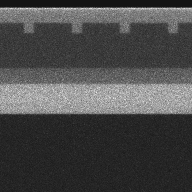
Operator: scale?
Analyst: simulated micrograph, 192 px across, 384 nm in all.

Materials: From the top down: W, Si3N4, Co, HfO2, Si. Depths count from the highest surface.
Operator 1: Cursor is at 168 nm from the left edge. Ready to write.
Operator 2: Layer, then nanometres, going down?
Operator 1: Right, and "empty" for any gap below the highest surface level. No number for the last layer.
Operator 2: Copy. W 30, Si3N4 90, Co 32, HfO2 60, Si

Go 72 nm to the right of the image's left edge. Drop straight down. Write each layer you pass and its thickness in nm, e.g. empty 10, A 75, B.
W 30, Si3N4 90, Co 32, HfO2 60, Si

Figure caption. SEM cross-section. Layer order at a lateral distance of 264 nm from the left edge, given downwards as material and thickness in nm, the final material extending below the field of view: W 30, Si3N4 90, Co 32, HfO2 60, Si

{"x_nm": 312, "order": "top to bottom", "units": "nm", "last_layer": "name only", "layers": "W 30, Si3N4 90, Co 32, HfO2 60, Si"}